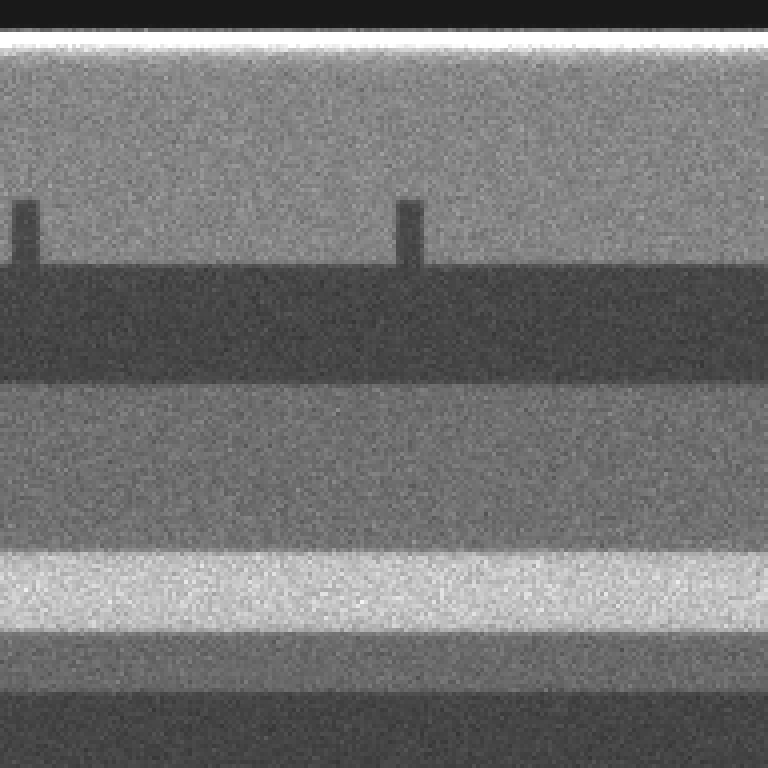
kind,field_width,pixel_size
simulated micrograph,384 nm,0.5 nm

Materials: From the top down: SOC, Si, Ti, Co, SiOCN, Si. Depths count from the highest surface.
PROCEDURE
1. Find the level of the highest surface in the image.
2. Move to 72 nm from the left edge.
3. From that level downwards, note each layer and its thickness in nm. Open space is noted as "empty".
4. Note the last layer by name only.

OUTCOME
SOC 116, Si 60, Ti 84, Co 40, SiOCN 30, Si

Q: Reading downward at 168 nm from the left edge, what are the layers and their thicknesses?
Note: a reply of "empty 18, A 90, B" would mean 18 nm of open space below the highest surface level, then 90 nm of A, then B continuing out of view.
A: SOC 116, Si 60, Ti 84, Co 40, SiOCN 30, Si